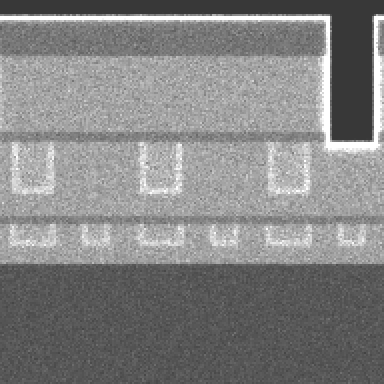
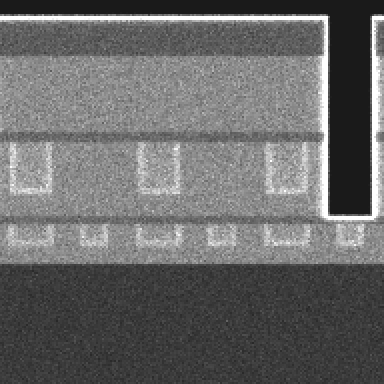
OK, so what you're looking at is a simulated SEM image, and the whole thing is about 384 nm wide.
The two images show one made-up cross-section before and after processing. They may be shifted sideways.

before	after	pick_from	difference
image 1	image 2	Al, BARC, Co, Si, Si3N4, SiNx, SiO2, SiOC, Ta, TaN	SiO2 removed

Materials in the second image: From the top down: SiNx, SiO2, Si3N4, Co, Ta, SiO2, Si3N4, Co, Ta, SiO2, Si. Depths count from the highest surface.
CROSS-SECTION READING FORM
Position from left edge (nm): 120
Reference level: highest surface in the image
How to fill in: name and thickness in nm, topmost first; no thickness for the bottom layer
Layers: SiNx 40, SiO2 76, Si3N4 10, SiO2 74, Si3N4 8, SiO2 40, Si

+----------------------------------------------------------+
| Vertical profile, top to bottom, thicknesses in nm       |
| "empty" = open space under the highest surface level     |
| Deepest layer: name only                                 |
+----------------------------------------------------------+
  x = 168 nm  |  SiNx 40, SiO2 76, Si3N4 10, Co 46, Ta 6, SiO2 22, Si3N4 8, Co 16, Ta 6, SiO2 18, Si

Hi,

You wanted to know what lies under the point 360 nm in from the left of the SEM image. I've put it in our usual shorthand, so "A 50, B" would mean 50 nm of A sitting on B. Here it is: empty 200, Si3N4 8, Ta 22, SiO2 18, Si